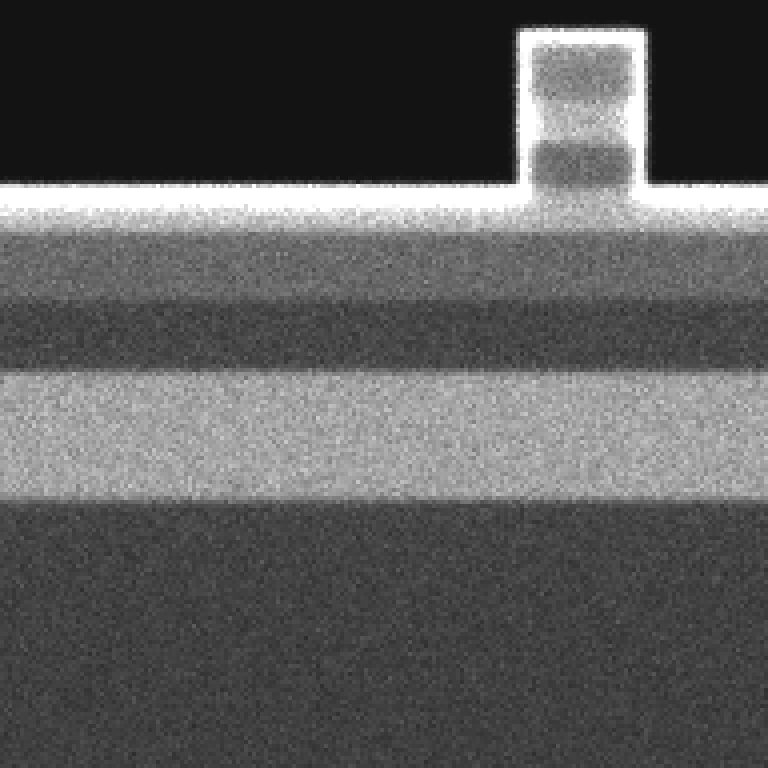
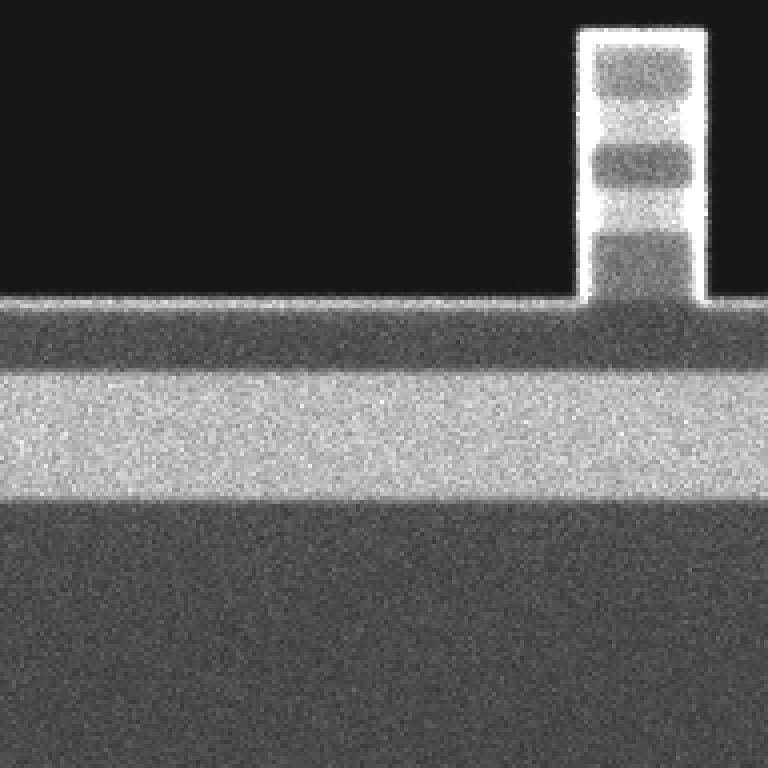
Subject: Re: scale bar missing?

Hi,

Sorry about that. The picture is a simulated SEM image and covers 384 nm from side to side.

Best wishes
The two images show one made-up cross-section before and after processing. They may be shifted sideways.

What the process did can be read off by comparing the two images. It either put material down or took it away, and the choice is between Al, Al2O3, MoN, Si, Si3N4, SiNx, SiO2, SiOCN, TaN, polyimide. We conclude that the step removed Al2O3 and SiOCN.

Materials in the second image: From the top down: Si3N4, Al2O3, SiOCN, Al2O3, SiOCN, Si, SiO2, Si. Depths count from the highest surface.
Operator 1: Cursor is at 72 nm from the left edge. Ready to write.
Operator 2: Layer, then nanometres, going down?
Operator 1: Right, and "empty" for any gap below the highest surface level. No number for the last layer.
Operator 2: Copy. empty 134, Si 36, SiO2 64, Si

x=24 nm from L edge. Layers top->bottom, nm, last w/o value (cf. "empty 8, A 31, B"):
empty 134, Si 36, SiO2 64, Si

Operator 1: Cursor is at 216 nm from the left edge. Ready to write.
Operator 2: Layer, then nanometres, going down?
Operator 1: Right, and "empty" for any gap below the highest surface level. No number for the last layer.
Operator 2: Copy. empty 134, Si 36, SiO2 64, Si